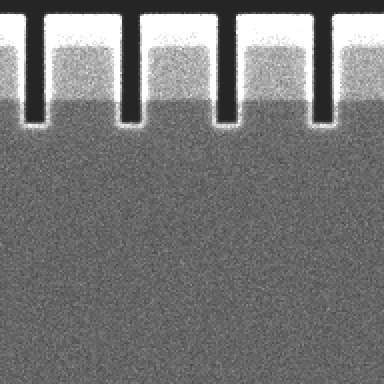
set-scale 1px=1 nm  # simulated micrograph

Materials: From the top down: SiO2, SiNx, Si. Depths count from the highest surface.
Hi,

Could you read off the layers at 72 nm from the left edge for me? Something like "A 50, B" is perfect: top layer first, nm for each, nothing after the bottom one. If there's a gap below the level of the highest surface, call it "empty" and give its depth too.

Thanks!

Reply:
SiO2 30, SiNx 54, Si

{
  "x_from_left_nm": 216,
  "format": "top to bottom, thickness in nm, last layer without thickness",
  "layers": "empty 108, Si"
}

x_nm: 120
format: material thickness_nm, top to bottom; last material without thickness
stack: empty 108, Si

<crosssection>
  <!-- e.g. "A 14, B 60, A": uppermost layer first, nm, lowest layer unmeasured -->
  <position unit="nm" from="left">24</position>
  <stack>empty 108, Si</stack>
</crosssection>